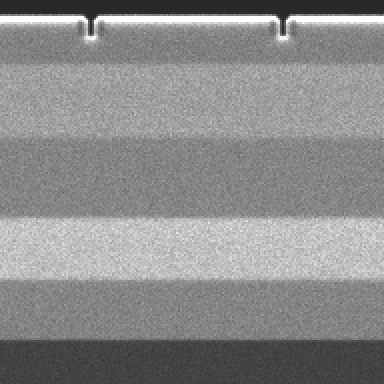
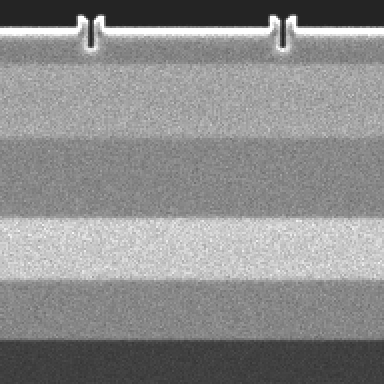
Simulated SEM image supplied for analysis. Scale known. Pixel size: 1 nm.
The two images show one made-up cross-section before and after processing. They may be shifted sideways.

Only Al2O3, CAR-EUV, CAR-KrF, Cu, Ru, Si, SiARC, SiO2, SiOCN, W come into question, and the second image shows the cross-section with SiO2 removed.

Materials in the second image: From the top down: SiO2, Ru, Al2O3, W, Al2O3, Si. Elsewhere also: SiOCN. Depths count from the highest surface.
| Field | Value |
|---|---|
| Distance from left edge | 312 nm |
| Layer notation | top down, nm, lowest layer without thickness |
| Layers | empty 12, SiO2 36, Ru 74, Al2O3 80, W 62, Al2O3 60, Si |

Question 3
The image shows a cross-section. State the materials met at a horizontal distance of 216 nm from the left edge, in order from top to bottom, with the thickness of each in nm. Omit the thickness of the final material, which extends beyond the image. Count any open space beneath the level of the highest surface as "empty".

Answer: empty 12, SiO2 36, Ru 74, Al2O3 80, W 62, Al2O3 60, Si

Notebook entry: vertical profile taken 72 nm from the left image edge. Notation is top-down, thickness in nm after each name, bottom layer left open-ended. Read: empty 12, SiO2 36, Ru 74, Al2O3 80, W 62, Al2O3 60, Si